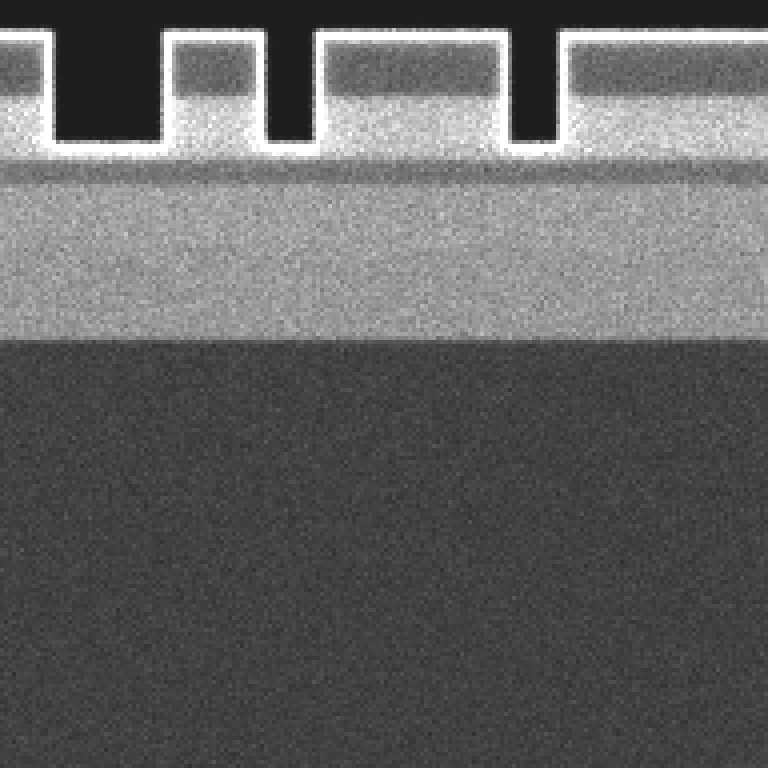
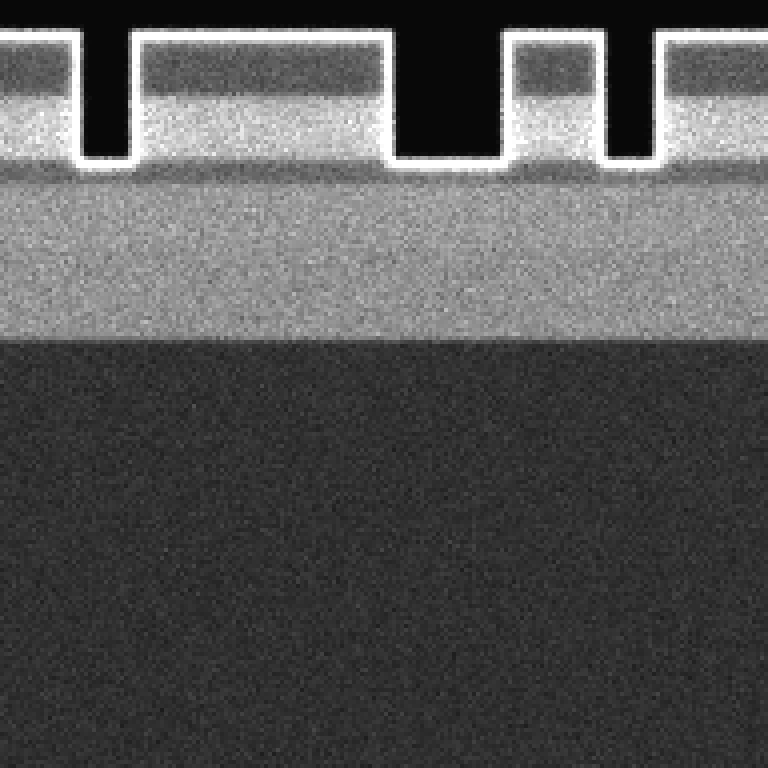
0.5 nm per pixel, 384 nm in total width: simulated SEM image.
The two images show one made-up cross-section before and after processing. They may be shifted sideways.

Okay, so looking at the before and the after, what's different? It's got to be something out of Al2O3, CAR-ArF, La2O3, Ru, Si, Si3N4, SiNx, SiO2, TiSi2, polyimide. Ru, removed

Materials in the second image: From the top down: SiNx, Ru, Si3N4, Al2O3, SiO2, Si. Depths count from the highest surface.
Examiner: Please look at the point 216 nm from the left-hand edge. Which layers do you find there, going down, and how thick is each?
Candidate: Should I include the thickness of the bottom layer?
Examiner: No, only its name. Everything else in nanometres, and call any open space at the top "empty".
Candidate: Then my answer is empty 64, Si3N4 12, Al2O3 32, SiO2 46, Si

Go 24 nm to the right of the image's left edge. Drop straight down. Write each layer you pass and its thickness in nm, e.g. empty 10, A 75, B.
SiNx 32, Ru 32, Si3N4 12, Al2O3 32, SiO2 46, Si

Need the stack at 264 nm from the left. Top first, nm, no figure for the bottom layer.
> SiNx 32, Ru 32, Si3N4 12, Al2O3 32, SiO2 46, Si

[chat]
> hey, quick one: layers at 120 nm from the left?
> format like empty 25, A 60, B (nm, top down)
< SiNx 32, Ru 32, Si3N4 12, Al2O3 32, SiO2 46, Si